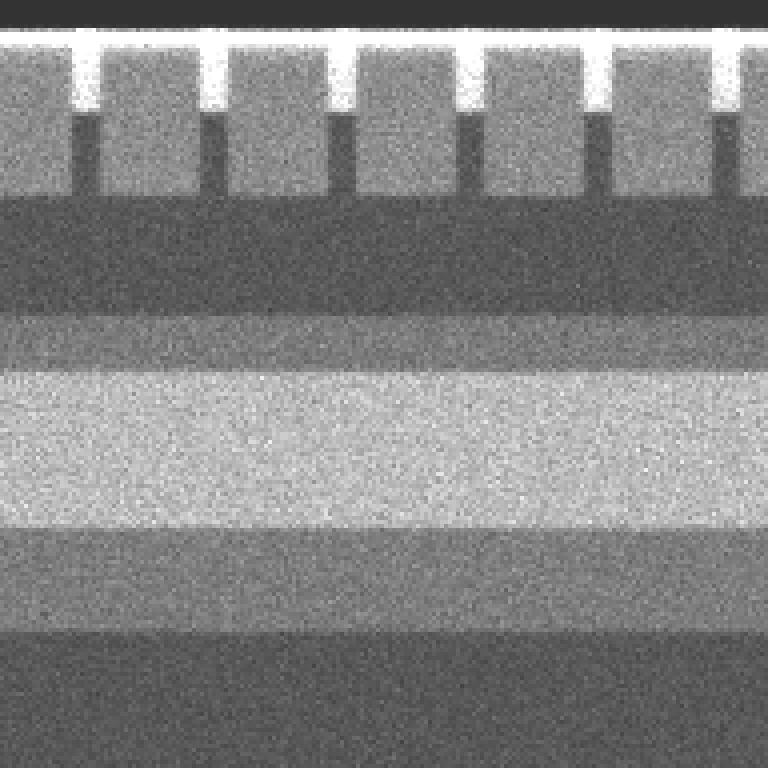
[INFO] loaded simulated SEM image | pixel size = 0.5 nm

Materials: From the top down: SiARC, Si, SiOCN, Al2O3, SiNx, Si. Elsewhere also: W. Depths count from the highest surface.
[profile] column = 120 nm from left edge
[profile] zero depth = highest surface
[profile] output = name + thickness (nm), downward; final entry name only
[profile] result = SiARC 82, Si 60, SiOCN 28, Al2O3 78, SiNx 52, Si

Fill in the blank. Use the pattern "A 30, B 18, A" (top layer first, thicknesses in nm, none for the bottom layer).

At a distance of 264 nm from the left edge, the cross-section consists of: SiARC 82, Si 60, SiOCN 28, Al2O3 78, SiNx 52, Si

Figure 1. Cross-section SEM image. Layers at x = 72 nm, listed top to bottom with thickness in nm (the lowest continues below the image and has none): SiARC 82, Si 60, SiOCN 28, Al2O3 78, SiNx 52, Si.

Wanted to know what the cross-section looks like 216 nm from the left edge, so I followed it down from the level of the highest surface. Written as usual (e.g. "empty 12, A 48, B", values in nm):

SiARC 82, Si 60, SiOCN 28, Al2O3 78, SiNx 52, Si